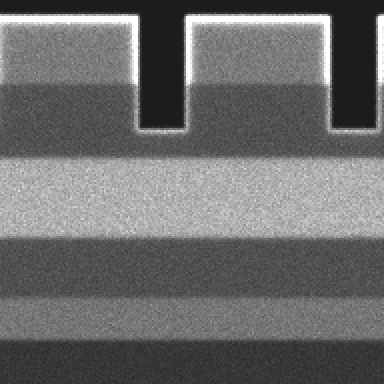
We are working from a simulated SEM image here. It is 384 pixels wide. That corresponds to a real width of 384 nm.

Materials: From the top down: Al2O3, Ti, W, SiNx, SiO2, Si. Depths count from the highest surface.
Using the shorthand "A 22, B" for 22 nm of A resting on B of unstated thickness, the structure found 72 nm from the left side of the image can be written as Al2O3 68, Ti 74, W 80, SiNx 60, SiO2 42, Si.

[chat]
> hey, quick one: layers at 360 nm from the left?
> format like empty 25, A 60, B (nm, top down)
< empty 114, Ti 28, W 80, SiNx 60, SiO2 42, Si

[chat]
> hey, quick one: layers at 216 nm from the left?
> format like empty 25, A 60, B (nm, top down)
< Al2O3 68, Ti 74, W 80, SiNx 60, SiO2 42, Si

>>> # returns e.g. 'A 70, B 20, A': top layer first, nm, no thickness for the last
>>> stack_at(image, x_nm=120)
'Al2O3 68, Ti 74, W 80, SiNx 60, SiO2 42, Si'